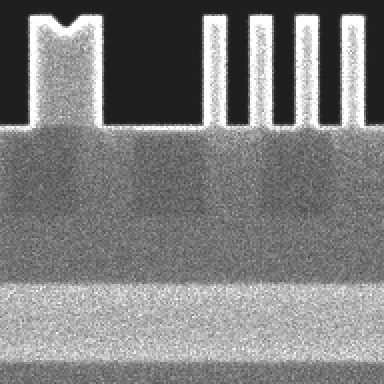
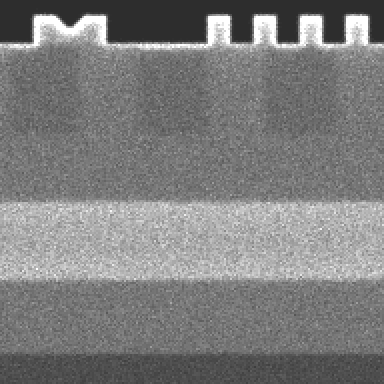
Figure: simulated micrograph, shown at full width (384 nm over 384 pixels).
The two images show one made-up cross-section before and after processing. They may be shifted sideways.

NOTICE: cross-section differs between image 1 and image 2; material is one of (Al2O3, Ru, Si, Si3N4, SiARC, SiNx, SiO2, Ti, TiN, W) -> removed: SiO2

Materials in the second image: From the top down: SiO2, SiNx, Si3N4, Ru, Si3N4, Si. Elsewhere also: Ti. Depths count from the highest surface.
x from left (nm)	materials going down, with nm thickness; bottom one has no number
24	empty 28, SiNx 90, Si3N4 68, Ru 78, Si3N4 74, Si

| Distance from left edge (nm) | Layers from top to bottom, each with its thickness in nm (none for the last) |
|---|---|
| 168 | empty 28, SiNx 90, Si3N4 68, Ru 78, Si3N4 74, Si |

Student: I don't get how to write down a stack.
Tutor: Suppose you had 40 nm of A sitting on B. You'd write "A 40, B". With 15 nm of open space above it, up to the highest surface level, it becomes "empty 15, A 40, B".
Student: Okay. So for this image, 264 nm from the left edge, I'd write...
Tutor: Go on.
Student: SiO2 28, Ti 110, Si3N4 48, Ru 78, Si3N4 74, Si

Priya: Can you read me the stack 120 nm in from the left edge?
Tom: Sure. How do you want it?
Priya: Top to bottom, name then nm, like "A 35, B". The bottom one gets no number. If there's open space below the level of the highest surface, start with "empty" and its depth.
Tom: empty 28, Ti 110, Si3N4 48, Ru 78, Si3N4 74, Si